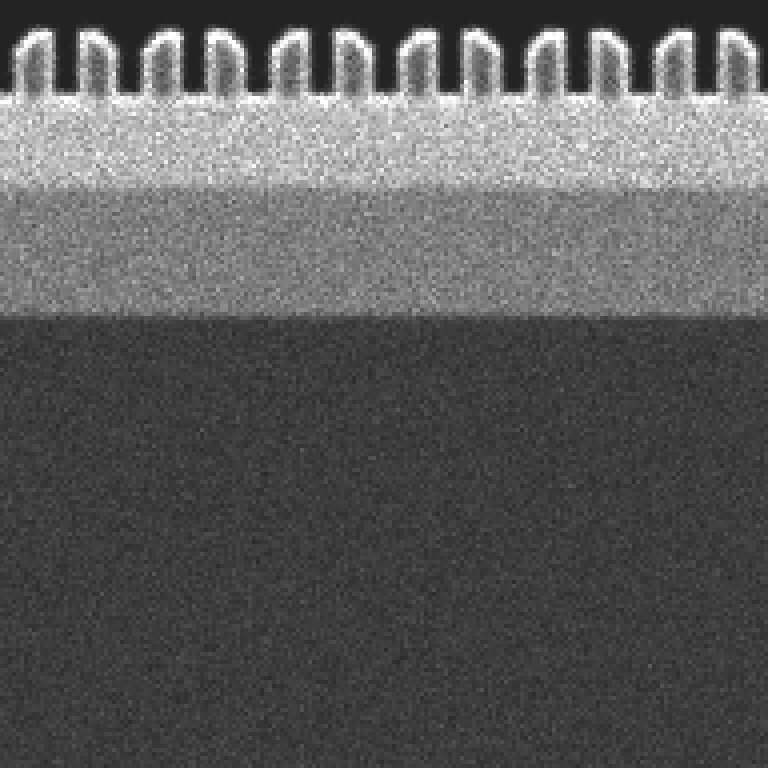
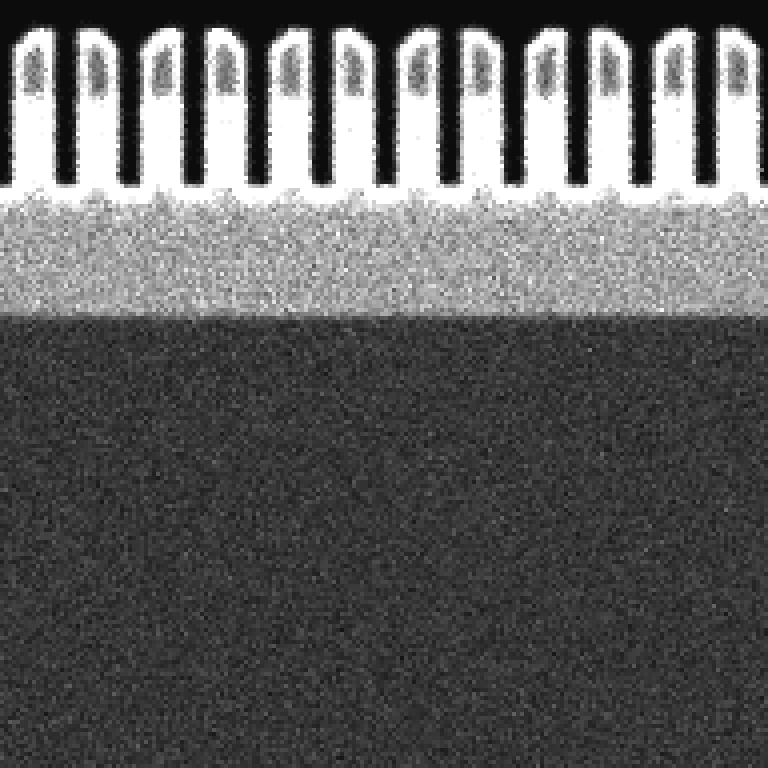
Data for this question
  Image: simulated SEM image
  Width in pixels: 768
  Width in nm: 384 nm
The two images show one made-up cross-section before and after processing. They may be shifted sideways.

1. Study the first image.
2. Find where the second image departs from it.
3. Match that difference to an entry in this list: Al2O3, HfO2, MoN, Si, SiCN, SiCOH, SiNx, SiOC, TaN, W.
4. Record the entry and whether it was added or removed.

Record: W / removed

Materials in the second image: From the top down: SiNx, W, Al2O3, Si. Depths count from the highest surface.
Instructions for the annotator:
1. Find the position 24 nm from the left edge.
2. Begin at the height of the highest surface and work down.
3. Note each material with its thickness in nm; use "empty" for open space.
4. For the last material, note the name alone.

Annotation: SiNx 32, W 46, Al2O3 64, Si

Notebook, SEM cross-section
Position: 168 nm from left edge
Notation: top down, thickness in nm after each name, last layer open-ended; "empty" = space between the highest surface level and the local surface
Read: SiNx 32, W 46, Al2O3 64, Si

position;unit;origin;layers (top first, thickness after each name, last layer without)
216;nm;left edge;SiNx 32, W 46, Al2O3 64, Si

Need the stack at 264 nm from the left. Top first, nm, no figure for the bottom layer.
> empty 8, SiNx 24, W 46, Al2O3 64, Si